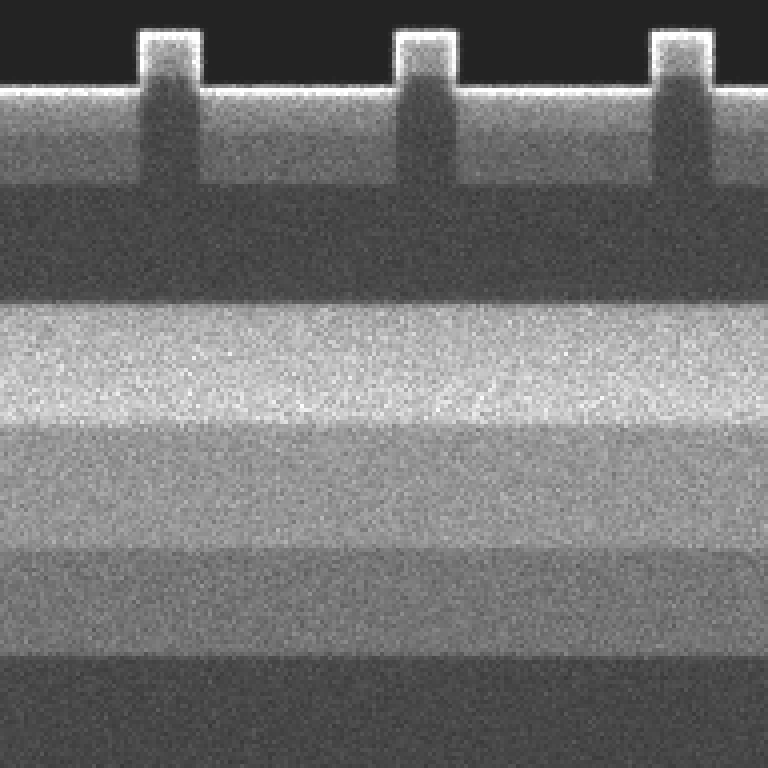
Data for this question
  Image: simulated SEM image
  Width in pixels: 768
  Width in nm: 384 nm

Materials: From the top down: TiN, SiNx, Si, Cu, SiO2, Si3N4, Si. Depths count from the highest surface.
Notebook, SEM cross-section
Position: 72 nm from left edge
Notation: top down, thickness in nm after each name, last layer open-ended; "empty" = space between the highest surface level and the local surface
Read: TiN 22, Si 114, Cu 60, SiO2 62, Si3N4 54, Si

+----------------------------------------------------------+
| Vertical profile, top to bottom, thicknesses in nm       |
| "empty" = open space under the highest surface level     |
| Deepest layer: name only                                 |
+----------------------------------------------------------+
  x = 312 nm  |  empty 28, TiN 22, SiNx 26, Si 60, Cu 60, SiO2 62, Si3N4 54, Si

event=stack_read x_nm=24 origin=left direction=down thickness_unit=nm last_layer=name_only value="empty 28, TiN 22, SiNx 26, Si 60, Cu 60, SiO2 62, Si3N4 54, Si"